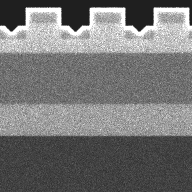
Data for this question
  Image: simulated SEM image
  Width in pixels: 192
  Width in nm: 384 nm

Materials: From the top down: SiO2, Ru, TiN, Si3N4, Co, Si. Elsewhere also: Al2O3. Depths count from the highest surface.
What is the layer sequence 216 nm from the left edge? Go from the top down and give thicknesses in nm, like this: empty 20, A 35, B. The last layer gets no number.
Al2O3 30, Ru 60, TiN 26, Si3N4 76, Co 64, Si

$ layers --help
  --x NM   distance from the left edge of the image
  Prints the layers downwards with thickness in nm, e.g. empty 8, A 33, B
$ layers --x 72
Al2O3 30, Ru 60, TiN 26, Si3N4 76, Co 64, Si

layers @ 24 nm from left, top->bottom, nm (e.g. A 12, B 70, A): empty 48, SiO2 14, Ru 28, TiN 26, Si3N4 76, Co 64, Si